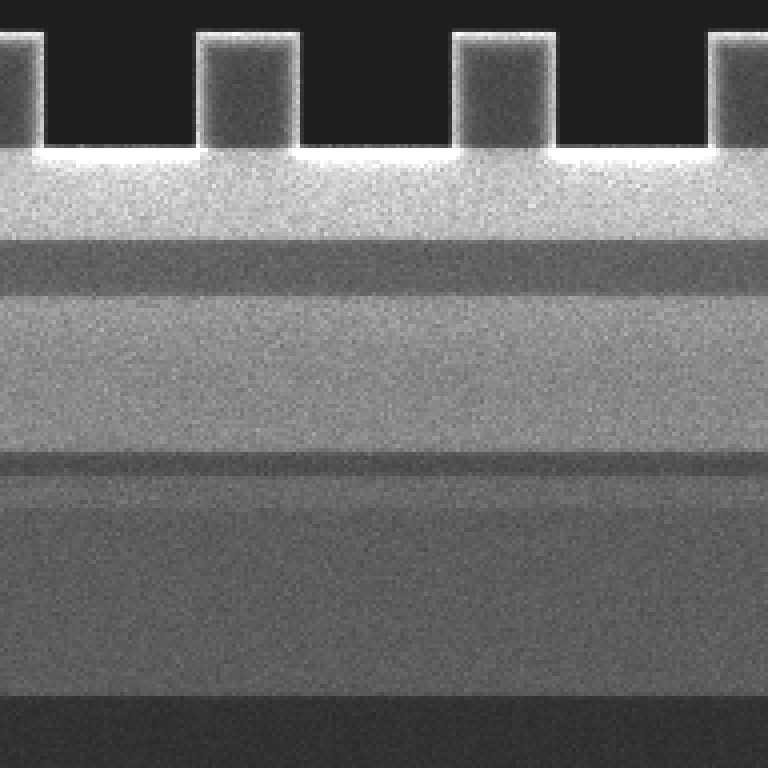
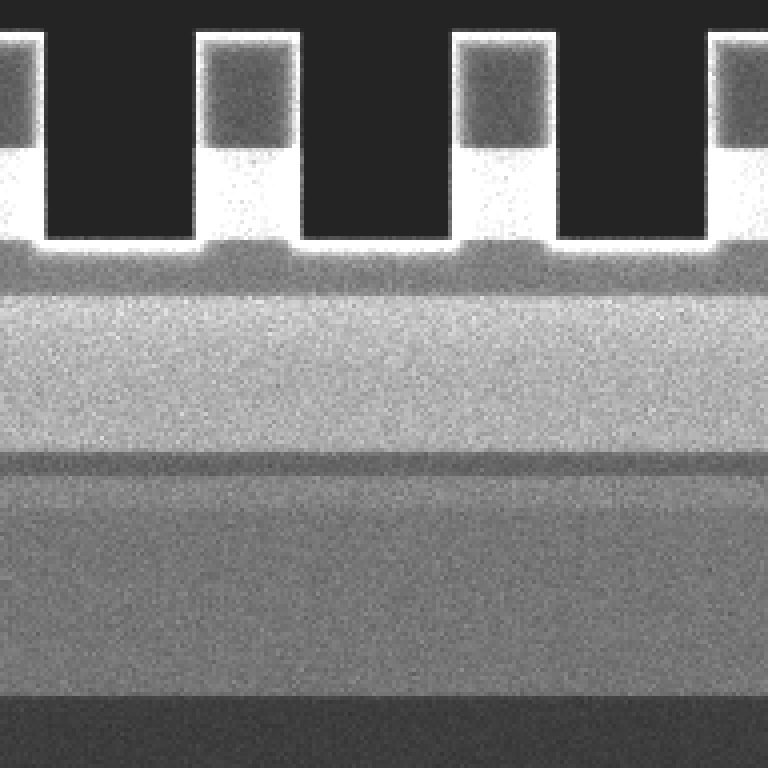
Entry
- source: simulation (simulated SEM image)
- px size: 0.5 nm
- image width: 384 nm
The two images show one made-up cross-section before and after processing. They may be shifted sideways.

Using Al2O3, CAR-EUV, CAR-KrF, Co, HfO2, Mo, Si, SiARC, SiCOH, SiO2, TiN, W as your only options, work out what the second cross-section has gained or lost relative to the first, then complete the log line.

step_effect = removed HfO2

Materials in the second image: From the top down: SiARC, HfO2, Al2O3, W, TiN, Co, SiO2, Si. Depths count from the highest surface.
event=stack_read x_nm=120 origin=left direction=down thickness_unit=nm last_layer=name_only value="SiARC 58, HfO2 46, Al2O3 28, W 78, TiN 12, Co 16, SiO2 94, Si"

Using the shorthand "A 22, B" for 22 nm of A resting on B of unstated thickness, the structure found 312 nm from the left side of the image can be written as empty 104, Al2O3 28, W 78, TiN 12, Co 16, SiO2 94, Si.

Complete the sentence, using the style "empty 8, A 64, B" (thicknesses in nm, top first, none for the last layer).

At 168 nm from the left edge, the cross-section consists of empty 104, Al2O3 28, W 78, TiN 12, Co 16, SiO2 94, Si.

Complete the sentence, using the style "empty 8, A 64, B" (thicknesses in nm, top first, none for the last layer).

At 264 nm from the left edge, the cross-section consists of SiARC 58, HfO2 46, Al2O3 28, W 78, TiN 12, Co 16, SiO2 94, Si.